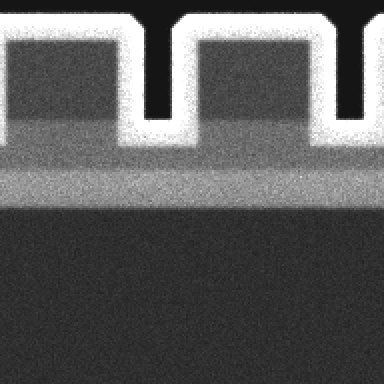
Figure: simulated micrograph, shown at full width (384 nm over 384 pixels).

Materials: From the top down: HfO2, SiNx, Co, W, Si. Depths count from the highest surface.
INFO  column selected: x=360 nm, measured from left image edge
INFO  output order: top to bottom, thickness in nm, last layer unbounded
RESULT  empty 106, HfO2 24, Co 24, W 38, Si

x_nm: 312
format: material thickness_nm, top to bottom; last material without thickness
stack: HfO2 130, Co 24, W 38, Si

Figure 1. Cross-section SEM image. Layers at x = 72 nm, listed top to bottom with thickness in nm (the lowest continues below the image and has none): HfO2 24, SiNx 80, Co 50, W 38, Si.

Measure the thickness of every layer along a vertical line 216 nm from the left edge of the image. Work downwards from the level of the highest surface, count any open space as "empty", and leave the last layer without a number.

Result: HfO2 24, SiNx 80, Co 50, W 38, Si